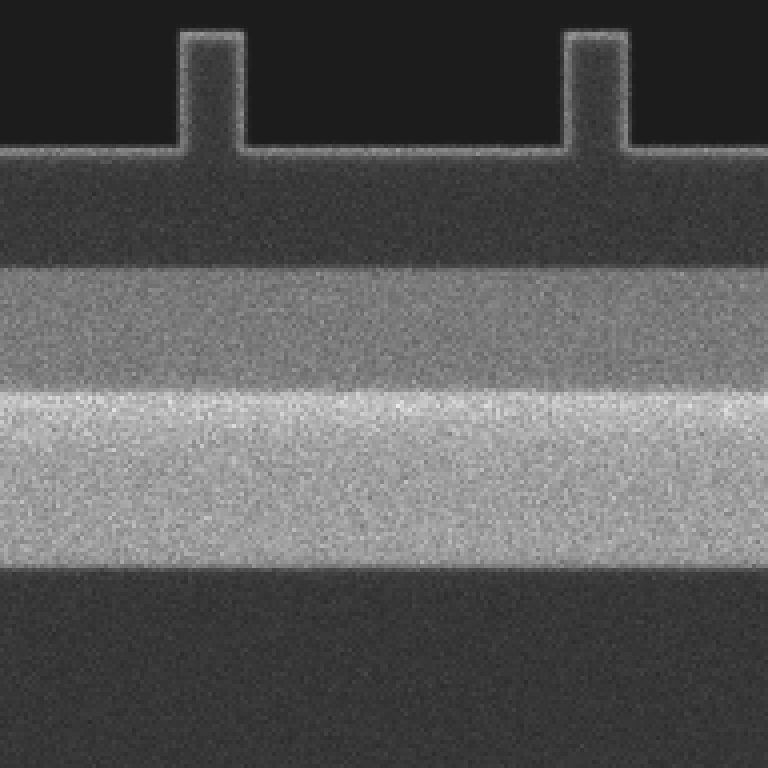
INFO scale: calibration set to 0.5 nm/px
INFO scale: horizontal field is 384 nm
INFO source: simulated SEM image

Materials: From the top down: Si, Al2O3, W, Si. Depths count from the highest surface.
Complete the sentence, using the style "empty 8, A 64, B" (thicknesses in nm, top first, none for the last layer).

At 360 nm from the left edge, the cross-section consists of empty 58, Si 60, Al2O3 62, W 88, Si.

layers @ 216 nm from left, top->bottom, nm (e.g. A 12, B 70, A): empty 58, Si 60, Al2O3 62, W 88, Si